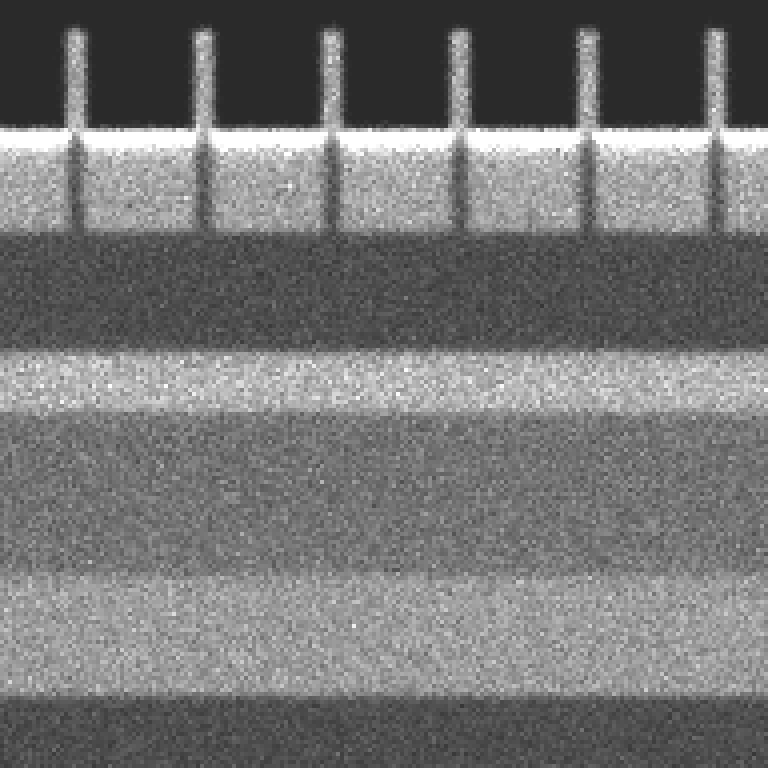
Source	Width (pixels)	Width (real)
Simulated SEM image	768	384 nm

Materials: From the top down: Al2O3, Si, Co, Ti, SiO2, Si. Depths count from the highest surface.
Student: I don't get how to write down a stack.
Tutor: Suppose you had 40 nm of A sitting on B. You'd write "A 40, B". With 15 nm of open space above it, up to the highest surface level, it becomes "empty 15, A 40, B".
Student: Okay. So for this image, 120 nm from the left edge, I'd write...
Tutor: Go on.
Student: empty 50, Al2O3 50, Si 60, Co 30, Ti 82, SiO2 60, Si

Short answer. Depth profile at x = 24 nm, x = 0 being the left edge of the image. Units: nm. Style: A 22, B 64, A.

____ empty 50, Al2O3 50, Si 60, Co 30, Ti 82, SiO2 60, Si